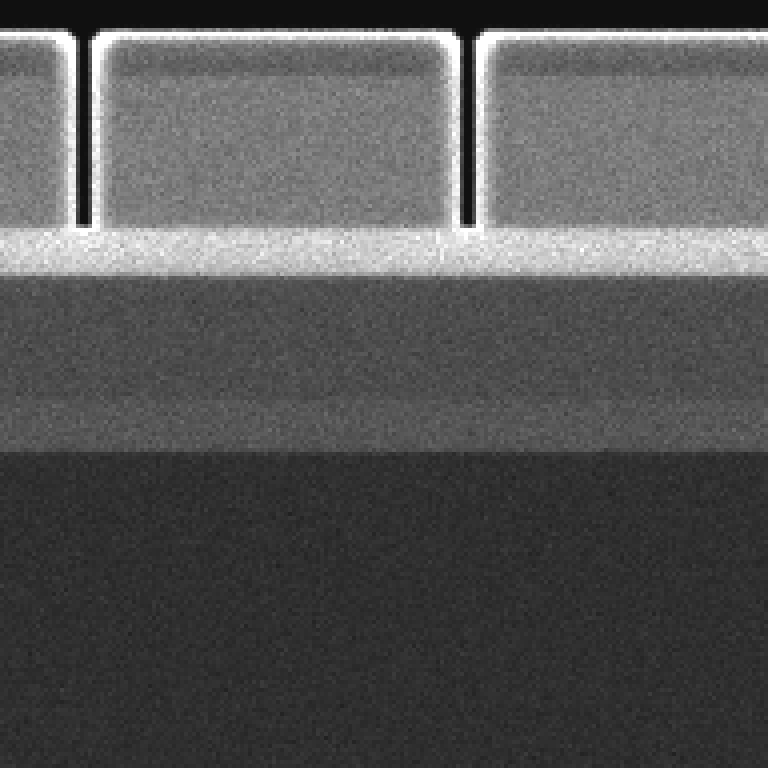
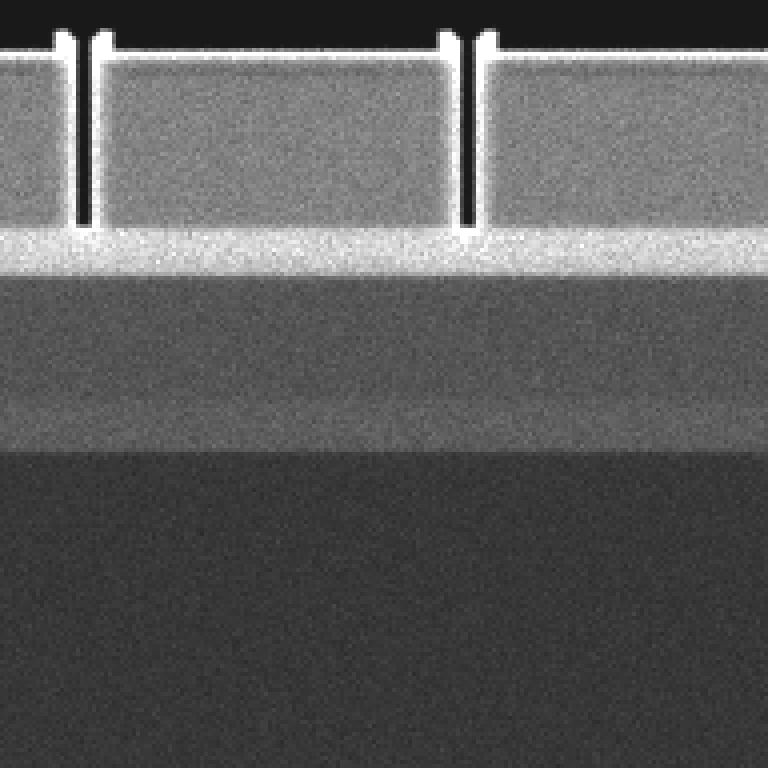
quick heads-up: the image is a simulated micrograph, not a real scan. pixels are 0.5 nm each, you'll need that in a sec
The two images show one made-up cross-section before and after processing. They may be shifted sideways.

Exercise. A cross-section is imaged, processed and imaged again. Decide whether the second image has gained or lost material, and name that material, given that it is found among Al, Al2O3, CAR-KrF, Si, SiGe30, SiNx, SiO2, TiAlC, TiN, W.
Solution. removed: TiN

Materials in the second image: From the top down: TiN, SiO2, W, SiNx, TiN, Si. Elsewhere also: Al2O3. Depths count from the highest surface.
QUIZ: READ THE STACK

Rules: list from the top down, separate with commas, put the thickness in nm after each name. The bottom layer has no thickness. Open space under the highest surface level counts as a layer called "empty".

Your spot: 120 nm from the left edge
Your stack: empty 10, TiN 12, SiO2 76, W 24, SiNx 62, TiN 26, Si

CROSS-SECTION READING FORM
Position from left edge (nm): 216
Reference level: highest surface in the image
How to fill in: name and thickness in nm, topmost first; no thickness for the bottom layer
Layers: empty 10, TiN 12, SiO2 76, W 24, SiNx 62, TiN 26, Si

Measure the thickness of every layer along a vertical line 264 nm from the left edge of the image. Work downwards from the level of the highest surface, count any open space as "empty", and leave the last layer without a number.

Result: empty 10, TiN 12, SiO2 76, W 24, SiNx 62, TiN 26, Si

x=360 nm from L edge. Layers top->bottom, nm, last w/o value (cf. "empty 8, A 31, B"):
empty 10, TiN 12, SiO2 76, W 24, SiNx 62, TiN 26, Si